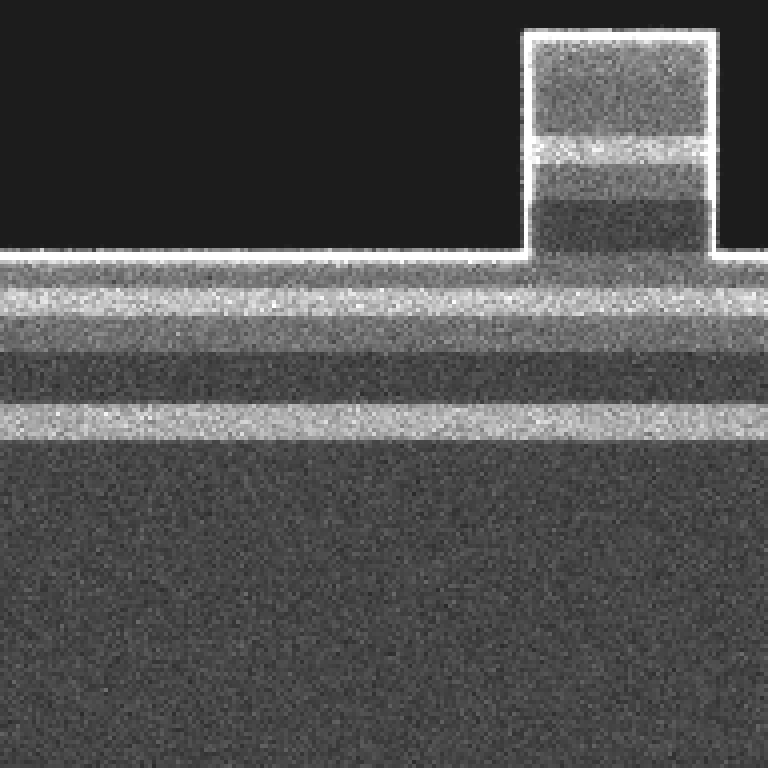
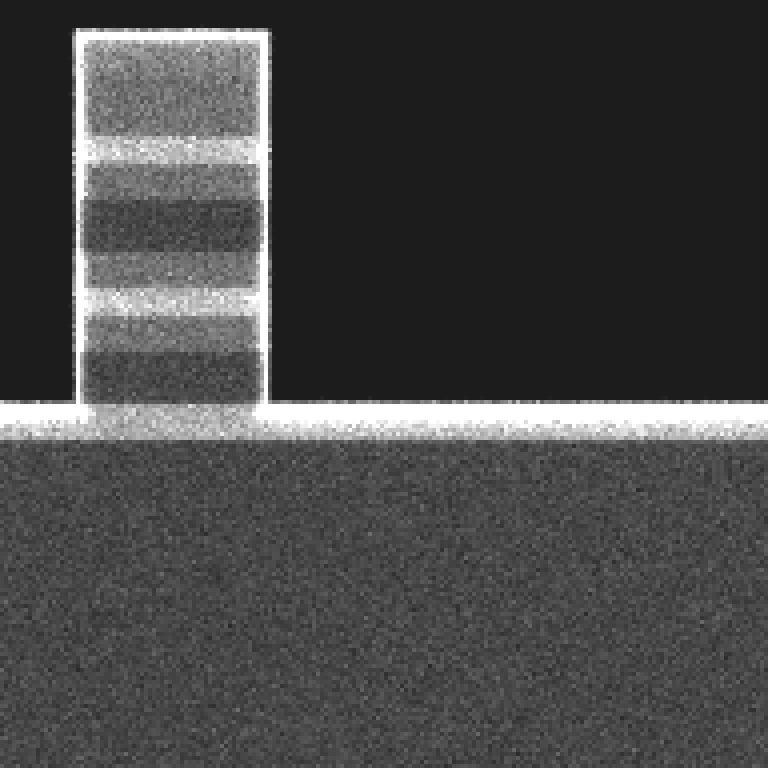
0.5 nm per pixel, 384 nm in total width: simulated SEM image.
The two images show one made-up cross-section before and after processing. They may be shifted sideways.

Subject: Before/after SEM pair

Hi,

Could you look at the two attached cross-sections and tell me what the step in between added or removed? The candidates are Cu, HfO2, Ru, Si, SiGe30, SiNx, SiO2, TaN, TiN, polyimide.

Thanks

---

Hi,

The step removed Ru and Si and SiNx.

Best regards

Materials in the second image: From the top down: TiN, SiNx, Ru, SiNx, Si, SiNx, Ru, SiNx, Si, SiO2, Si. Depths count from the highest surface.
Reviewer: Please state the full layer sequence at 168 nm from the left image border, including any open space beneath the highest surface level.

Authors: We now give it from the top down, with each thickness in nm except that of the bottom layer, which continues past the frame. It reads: empty 186, SiO2 18, Si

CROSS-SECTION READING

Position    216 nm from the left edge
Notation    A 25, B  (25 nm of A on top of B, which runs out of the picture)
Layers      empty 186, SiO2 18, Si